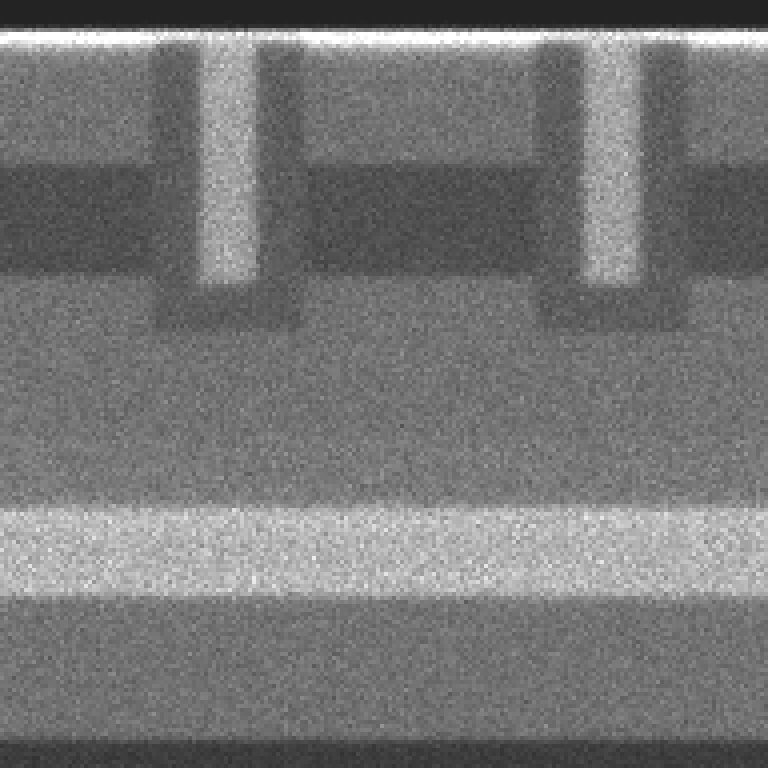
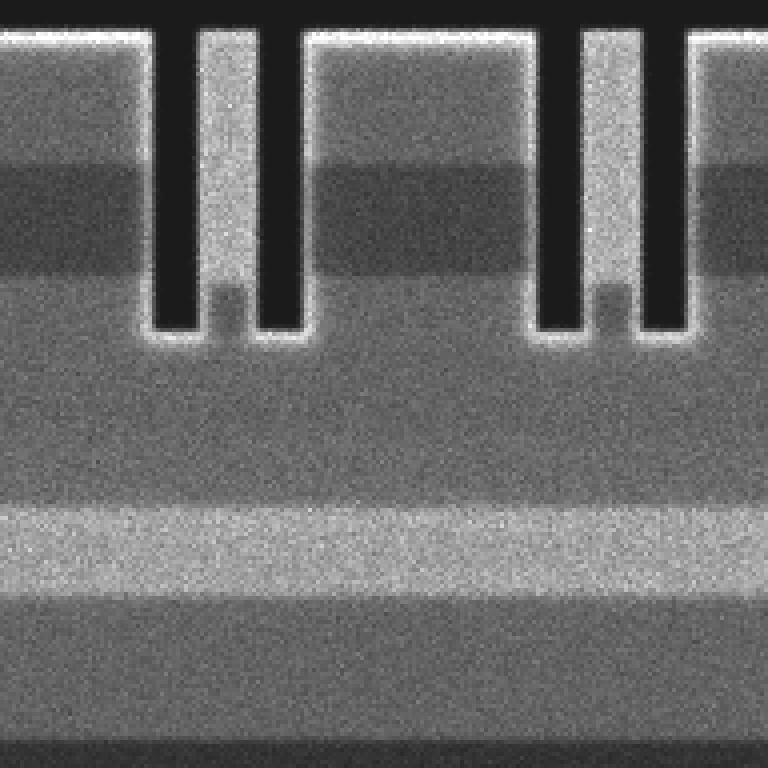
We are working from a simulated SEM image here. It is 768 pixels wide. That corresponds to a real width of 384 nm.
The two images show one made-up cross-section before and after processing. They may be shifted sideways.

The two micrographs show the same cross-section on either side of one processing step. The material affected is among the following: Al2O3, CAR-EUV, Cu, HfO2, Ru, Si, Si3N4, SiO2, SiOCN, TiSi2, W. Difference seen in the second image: Si3N4 removed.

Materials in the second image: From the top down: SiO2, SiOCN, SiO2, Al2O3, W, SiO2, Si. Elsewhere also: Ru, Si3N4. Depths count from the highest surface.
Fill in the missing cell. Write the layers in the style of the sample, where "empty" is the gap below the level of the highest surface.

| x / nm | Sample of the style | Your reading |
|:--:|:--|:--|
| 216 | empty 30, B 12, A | SiO2 66, SiOCN 56, SiO2 80, Al2O3 36, W 44, SiO2 72, Si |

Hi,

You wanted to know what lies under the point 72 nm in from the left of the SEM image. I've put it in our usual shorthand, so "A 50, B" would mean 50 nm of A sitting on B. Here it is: SiO2 66, SiOCN 56, SiO2 80, Al2O3 36, W 44, SiO2 72, Si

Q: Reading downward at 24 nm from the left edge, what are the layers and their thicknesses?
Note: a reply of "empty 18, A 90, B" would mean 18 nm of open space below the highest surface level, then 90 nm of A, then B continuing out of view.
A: SiO2 66, SiOCN 56, SiO2 80, Al2O3 36, W 44, SiO2 72, Si